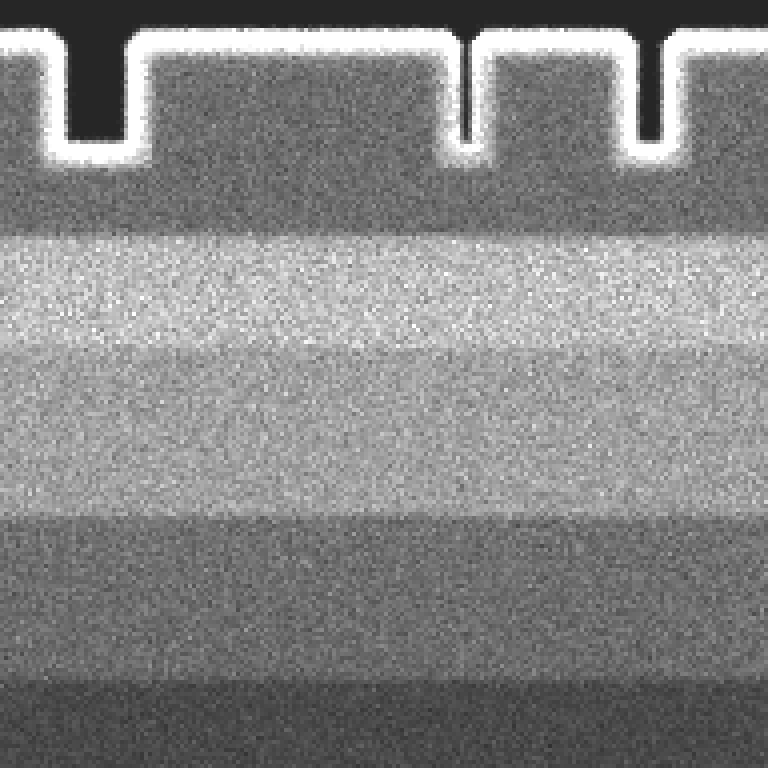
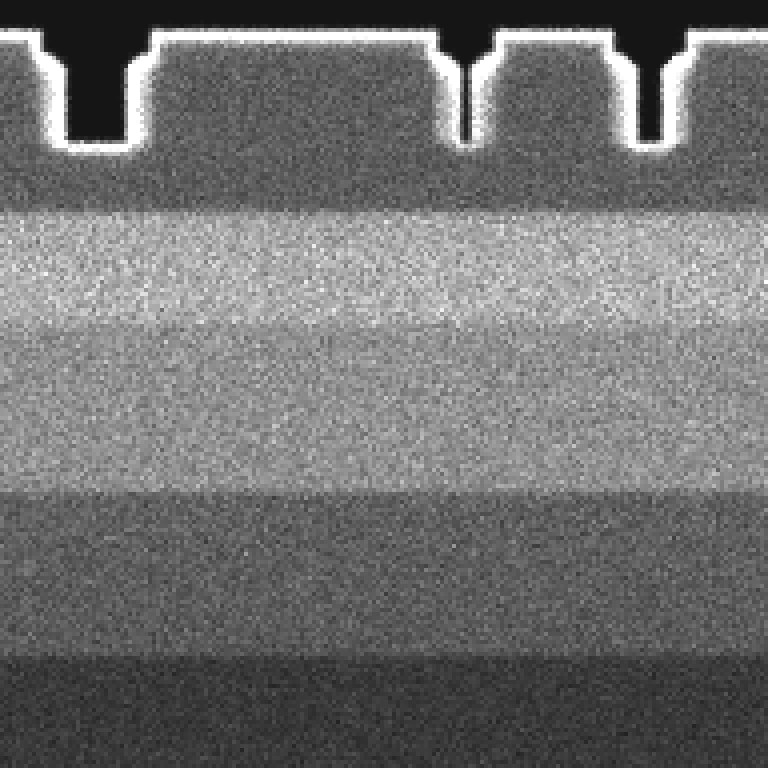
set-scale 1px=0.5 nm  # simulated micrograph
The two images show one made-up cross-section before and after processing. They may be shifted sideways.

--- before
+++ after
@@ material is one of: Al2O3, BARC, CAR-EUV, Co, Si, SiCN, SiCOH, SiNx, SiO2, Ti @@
Al2O3 removed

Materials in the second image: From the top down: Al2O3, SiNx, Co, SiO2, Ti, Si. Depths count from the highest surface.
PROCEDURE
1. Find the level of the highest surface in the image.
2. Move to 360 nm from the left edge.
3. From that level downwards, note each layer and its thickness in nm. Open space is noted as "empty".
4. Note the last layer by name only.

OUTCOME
SiNx 90, Co 56, SiO2 84, Ti 82, Si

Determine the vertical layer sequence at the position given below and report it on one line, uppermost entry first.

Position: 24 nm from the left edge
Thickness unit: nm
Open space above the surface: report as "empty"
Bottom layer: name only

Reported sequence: empty 12, Al2O3 44, SiNx 34, Co 56, SiO2 84, Ti 82, Si